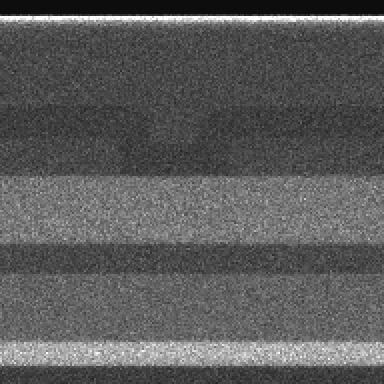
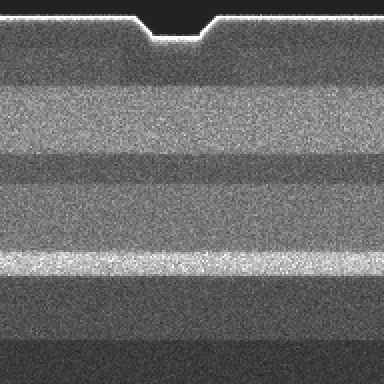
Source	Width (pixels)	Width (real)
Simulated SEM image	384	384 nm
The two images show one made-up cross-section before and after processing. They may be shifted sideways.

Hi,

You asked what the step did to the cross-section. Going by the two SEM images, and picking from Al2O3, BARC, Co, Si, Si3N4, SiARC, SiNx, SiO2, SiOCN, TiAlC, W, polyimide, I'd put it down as SiARC, removed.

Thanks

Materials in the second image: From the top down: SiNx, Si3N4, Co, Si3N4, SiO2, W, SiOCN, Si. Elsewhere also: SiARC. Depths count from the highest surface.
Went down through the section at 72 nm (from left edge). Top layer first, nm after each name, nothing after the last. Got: SiNx 32, Si3N4 38, Co 68, Si3N4 30, SiO2 68, W 24, SiOCN 64, Si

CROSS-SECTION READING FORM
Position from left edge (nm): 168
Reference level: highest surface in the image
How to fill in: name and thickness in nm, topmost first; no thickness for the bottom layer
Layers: empty 20, SiARC 18, SiNx 32, Co 68, Si3N4 30, SiO2 68, W 24, SiOCN 64, Si